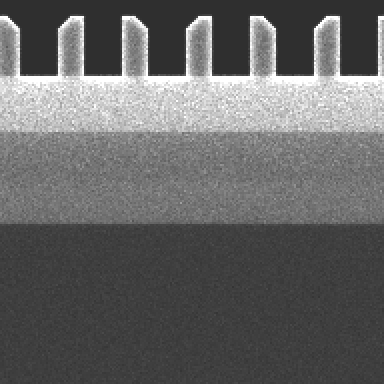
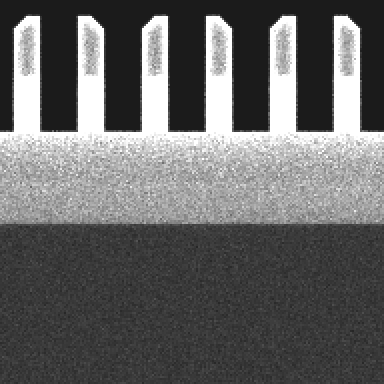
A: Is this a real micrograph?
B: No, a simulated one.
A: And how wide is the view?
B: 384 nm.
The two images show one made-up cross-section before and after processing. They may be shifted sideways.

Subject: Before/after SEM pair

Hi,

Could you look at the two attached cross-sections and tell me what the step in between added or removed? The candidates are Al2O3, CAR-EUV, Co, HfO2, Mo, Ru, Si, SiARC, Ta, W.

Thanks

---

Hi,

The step removed HfO2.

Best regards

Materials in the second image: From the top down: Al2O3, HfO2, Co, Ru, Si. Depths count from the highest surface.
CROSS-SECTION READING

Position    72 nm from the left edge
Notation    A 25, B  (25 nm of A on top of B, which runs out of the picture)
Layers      empty 116, Co 50, Ru 42, Si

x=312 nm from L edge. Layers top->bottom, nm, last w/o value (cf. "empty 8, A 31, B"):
empty 116, Co 50, Ru 42, Si